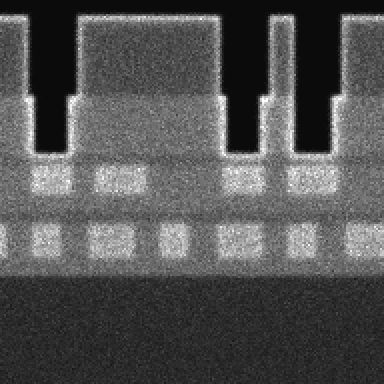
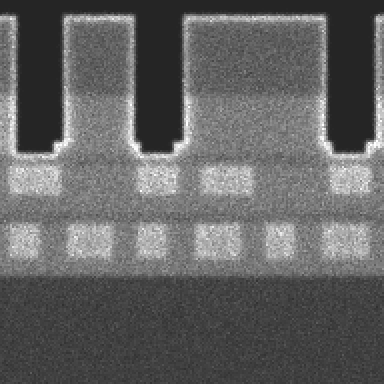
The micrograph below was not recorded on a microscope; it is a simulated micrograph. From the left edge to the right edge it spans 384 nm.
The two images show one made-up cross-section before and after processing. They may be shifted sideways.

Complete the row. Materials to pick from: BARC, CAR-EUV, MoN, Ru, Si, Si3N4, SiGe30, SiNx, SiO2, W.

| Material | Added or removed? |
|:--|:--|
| SiO2 | removed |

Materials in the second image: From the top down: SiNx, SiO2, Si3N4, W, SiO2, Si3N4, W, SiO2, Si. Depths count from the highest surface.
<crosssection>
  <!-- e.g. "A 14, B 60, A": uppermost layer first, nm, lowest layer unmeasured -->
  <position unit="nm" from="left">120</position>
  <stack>SiNx 80, SiO2 58, Si3N4 12, SiO2 46, Si3N4 12, SiO2 52, Si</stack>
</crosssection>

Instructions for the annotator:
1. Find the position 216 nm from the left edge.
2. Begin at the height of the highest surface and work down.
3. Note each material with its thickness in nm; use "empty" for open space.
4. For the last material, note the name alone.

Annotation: SiNx 80, SiO2 58, Si3N4 12, W 28, SiO2 18, Si3N4 12, W 34, SiO2 18, Si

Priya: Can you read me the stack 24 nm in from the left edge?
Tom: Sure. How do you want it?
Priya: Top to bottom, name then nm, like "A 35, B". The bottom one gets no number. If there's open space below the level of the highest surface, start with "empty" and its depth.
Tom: empty 138, Si3N4 12, W 28, SiO2 18, Si3N4 12, W 34, SiO2 18, Si